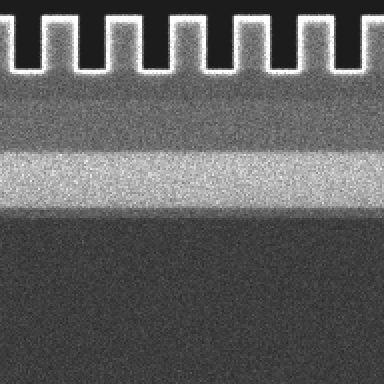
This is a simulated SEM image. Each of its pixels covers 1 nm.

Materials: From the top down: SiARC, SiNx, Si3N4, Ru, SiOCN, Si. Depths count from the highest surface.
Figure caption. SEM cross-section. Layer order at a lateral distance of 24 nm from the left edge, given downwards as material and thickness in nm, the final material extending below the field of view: empty 54, SiNx 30, Si3N4 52, Ru 56, SiOCN 10, Si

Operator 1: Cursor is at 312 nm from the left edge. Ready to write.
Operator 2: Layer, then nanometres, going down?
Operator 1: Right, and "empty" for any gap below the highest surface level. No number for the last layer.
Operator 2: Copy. SiARC 54, SiNx 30, Si3N4 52, Ru 56, SiOCN 10, Si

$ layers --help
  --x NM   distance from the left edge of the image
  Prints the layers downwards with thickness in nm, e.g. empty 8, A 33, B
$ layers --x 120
SiARC 54, SiNx 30, Si3N4 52, Ru 56, SiOCN 10, Si